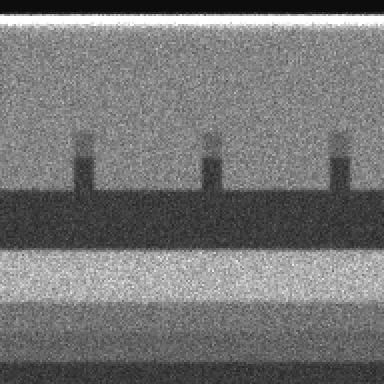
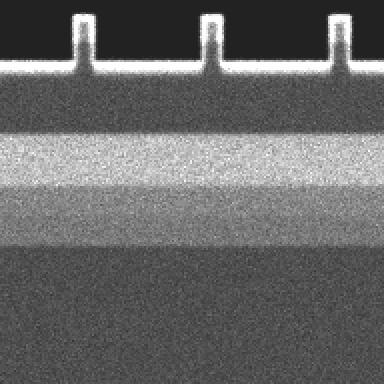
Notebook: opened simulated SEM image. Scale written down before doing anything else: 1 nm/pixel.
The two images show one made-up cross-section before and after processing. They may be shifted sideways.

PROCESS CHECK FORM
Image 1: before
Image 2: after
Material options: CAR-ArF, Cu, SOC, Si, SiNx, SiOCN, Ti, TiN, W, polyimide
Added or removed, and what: removed, SOC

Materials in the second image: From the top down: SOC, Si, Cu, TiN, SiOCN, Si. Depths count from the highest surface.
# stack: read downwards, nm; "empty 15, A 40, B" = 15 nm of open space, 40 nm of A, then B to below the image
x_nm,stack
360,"empty 46, SOC 12, Si 60, Cu 52, TiN 30, SiOCN 30, Si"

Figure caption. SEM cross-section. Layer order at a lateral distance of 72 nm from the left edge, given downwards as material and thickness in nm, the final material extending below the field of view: empty 46, SOC 12, Si 60, Cu 52, TiN 30, SiOCN 30, Si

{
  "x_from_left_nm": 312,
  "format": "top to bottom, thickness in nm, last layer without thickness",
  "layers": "empty 46, SOC 12, Si 60, Cu 52, TiN 30, SiOCN 30, Si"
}